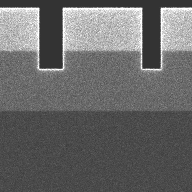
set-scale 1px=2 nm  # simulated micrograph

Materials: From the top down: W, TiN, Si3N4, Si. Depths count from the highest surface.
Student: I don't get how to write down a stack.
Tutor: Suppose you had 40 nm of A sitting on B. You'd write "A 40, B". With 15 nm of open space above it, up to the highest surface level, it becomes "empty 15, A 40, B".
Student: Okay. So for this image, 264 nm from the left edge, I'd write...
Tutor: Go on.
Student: W 86, TiN 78, Si3N4 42, Si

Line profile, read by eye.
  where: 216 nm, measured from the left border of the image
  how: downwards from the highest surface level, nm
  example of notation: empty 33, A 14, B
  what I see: W 86, TiN 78, Si3N4 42, Si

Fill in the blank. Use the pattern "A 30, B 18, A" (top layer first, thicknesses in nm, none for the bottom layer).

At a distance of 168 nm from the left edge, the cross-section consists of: W 86, TiN 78, Si3N4 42, Si